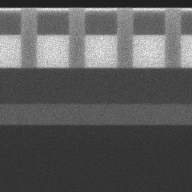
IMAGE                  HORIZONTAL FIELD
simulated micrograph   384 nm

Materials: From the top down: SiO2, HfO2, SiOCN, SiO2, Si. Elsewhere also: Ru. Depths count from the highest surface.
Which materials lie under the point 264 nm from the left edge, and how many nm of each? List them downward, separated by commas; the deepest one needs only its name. Ru 120, SiOCN 72, SiO2 42, Si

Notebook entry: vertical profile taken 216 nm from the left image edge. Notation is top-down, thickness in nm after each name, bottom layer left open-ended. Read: SiO2 54, HfO2 66, SiOCN 72, SiO2 42, Si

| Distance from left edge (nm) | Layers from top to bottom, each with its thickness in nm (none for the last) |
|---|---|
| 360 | Ru 120, SiOCN 72, SiO2 42, Si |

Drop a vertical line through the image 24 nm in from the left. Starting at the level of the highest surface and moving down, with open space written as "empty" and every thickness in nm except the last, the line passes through SiO2 54, HfO2 66, SiOCN 72, SiO2 42, Si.